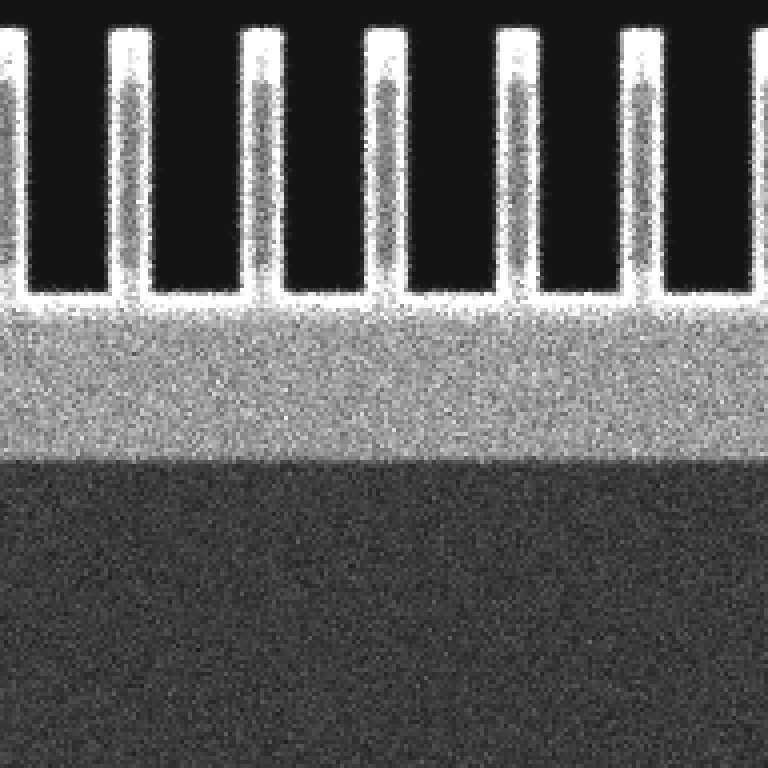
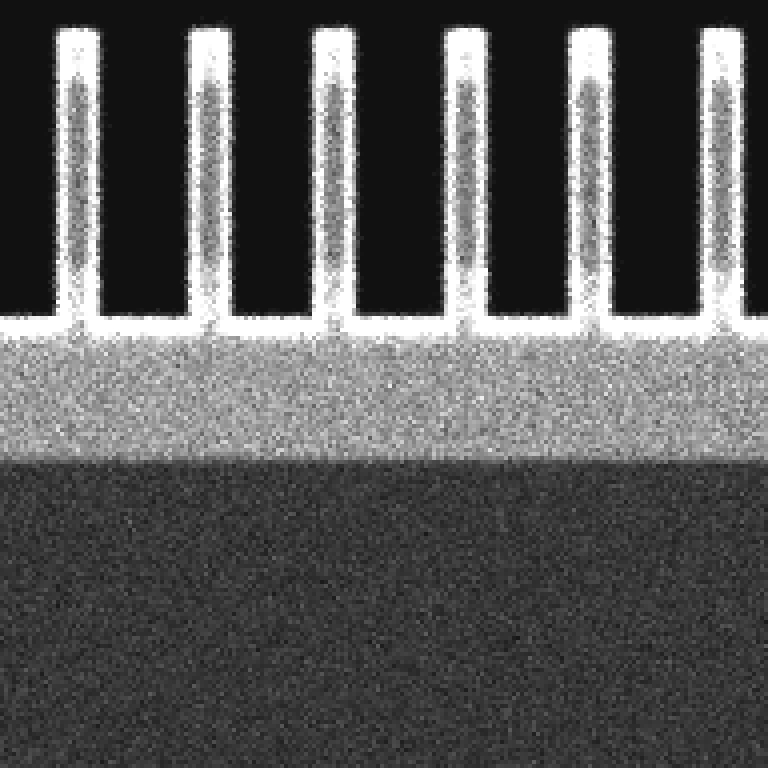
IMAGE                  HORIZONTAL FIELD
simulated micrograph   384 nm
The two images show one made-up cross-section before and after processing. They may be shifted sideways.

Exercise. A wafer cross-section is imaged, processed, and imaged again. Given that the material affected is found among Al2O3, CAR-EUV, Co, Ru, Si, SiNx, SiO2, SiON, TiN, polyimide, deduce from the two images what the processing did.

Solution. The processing removed Ru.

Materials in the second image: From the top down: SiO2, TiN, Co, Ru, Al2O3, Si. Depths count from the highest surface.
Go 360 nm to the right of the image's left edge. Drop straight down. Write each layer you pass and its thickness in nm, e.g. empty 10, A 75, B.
SiO2 24, TiN 94, Co 14, Ru 12, Al2O3 70, Si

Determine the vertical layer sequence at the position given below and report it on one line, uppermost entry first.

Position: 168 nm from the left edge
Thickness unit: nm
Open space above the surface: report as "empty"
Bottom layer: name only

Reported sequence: SiO2 24, TiN 94, Co 14, Ru 12, Al2O3 70, Si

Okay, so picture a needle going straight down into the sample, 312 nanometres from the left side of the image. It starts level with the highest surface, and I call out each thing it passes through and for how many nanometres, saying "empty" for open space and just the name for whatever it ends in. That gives empty 144, Al2O3 70, Si